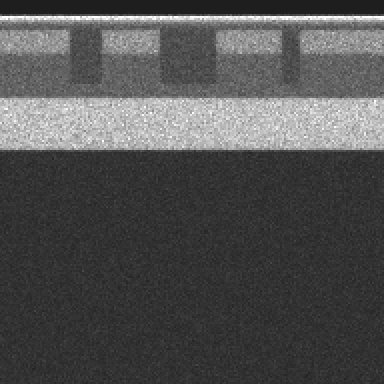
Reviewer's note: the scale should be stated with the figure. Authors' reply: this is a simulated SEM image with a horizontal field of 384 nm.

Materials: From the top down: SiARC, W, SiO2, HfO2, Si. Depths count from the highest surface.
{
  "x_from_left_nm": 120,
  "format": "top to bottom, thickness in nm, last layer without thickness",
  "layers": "SiARC 14, W 24, SiO2 44, HfO2 52, Si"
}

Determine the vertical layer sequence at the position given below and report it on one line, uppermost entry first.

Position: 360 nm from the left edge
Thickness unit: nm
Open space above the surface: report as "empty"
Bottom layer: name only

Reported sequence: SiARC 14, W 24, SiO2 44, HfO2 52, Si